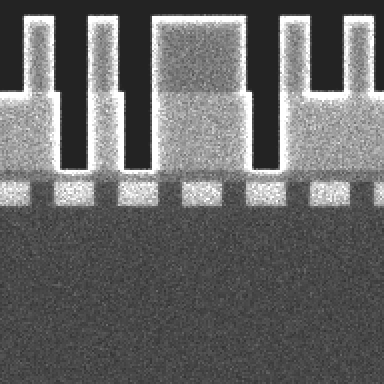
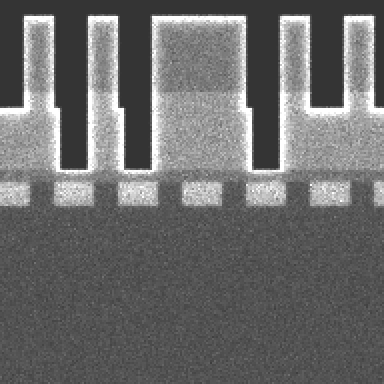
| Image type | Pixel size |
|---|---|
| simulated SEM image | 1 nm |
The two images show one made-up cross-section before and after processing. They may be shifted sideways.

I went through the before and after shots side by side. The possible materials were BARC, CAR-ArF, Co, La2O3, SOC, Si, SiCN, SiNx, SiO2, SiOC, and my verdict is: removed, SiO2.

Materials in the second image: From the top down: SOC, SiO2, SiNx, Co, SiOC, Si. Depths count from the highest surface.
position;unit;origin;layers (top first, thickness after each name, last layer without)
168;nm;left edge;SOC 76, SiO2 78, SiNx 12, SiOC 36, Si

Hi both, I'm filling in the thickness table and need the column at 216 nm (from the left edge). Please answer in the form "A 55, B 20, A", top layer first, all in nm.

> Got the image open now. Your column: SOC 76, SiO2 78, SiNx 12, Co 24, SiOC 12, Si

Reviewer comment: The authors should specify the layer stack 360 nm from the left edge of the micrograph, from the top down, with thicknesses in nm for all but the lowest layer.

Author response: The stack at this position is SOC 76, SiO2 78, SiNx 12, SiOC 36, Si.